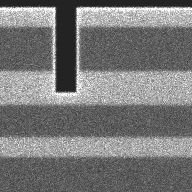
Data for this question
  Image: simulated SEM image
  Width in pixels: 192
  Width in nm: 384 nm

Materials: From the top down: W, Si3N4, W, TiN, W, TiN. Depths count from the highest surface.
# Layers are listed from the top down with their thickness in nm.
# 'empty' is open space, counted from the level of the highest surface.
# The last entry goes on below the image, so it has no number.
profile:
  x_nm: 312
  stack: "W 38, Si3N4 88, W 68, TiN 64, W 40, TiN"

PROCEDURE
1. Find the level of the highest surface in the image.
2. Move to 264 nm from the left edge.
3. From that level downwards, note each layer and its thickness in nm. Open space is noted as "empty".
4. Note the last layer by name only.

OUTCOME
W 38, Si3N4 88, W 68, TiN 64, W 40, TiN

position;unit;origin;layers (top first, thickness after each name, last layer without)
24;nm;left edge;W 38, Si3N4 88, W 68, TiN 64, W 40, TiN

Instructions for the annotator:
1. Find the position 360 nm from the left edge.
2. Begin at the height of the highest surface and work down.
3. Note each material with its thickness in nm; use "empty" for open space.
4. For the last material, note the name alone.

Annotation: W 38, Si3N4 88, W 68, TiN 64, W 40, TiN